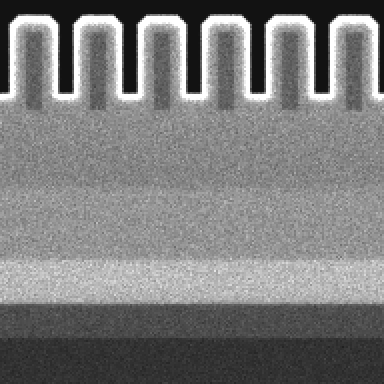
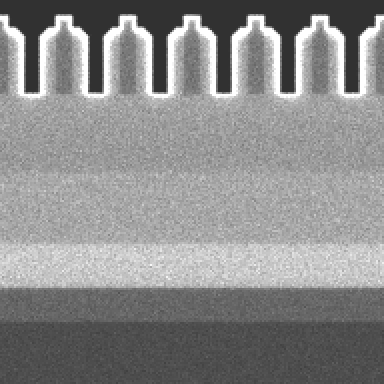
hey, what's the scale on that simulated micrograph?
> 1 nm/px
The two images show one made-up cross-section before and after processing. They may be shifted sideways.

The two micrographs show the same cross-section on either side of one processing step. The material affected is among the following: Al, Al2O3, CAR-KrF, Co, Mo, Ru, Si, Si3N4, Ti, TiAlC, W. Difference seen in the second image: Al2O3 removed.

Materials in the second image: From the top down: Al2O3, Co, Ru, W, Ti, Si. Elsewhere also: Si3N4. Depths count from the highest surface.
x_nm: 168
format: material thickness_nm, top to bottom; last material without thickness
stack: empty 20, Al2O3 58, Co 78, Ru 72, W 44, Ti 34, Si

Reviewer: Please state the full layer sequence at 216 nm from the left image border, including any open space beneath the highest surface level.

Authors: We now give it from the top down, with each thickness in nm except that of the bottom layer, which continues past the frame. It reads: empty 78, Co 78, Ru 72, W 44, Ti 34, Si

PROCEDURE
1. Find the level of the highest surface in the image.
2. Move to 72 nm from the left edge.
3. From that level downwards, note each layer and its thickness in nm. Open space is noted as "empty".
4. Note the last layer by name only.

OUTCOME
empty 12, Al2O3 66, Co 78, Ru 72, W 44, Ti 34, Si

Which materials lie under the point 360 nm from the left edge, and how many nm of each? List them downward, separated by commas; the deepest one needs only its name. empty 20, Al2O3 58, Co 78, Ru 72, W 44, Ti 34, Si